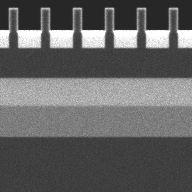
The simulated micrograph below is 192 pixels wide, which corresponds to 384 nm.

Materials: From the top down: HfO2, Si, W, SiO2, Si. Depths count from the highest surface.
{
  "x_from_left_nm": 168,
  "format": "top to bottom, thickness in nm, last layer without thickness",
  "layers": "empty 46, HfO2 34, Si 60, W 56, SiO2 62, Si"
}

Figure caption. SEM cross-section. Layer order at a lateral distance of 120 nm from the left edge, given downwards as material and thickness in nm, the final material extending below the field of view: empty 46, HfO2 34, Si 60, W 56, SiO2 62, Si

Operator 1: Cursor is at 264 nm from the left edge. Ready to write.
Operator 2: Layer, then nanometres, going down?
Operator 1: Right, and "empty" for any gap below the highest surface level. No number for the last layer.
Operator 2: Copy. empty 46, HfO2 34, Si 60, W 56, SiO2 62, Si